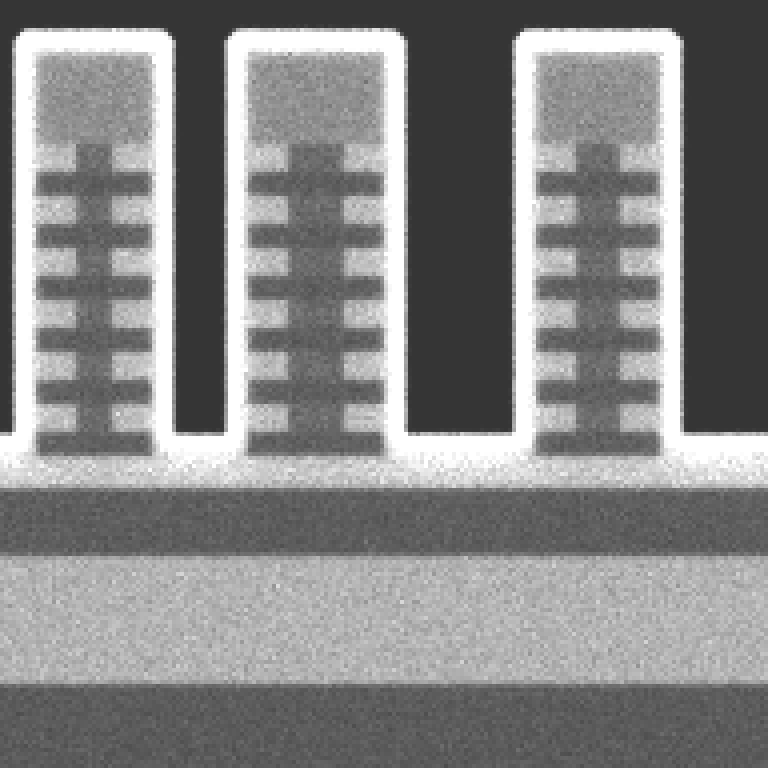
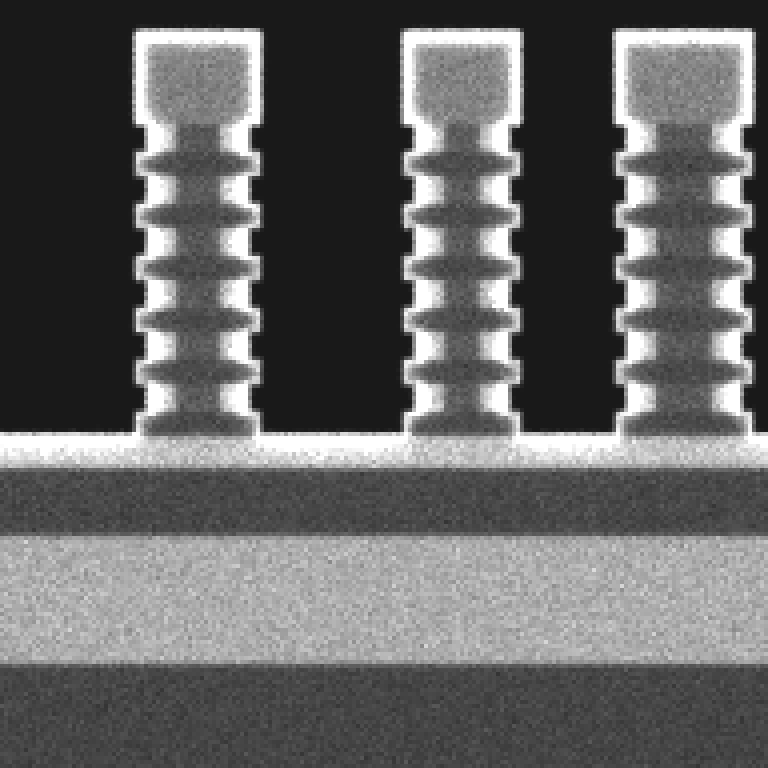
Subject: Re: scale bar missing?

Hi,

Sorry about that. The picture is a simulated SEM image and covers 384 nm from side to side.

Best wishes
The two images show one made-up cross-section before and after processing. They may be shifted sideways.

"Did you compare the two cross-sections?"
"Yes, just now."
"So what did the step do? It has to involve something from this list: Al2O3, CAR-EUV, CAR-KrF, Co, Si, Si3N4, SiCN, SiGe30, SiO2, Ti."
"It removed Al2O3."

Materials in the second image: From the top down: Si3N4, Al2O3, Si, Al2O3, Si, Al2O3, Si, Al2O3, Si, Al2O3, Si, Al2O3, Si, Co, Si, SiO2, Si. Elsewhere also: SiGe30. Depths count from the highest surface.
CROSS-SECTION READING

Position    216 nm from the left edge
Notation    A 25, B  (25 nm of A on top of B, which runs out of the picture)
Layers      Si3N4 46, Al2O3 14, Si 12, Al2O3 14, Si 12, Al2O3 14, Si 12, Al2O3 14, Si 12, Al2O3 14, Si 12, Al2O3 14, Si 12, Co 16, Si 34, SiO2 64, Si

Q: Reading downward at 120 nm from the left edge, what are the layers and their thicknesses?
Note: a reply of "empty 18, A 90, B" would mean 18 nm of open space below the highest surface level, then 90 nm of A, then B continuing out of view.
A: Si3N4 46, Al2O3 14, Si 12, Al2O3 14, Si 12, Al2O3 14, Si 12, Al2O3 14, Si 12, Al2O3 14, Si 12, Al2O3 14, Si 12, Co 16, Si 34, SiO2 64, Si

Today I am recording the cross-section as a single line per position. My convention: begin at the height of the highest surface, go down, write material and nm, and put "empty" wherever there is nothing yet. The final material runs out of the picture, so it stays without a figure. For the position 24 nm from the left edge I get empty 202, Co 16, Si 34, SiO2 64, Si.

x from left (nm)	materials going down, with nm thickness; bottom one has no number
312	Si3N4 46, empty 14, Si 12, empty 14, Si 12, empty 14, Si 12, empty 14, Si 12, empty 14, Si 12, empty 14, Si 12, Co 16, Si 34, SiO2 64, Si